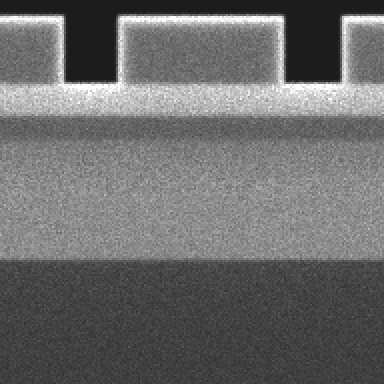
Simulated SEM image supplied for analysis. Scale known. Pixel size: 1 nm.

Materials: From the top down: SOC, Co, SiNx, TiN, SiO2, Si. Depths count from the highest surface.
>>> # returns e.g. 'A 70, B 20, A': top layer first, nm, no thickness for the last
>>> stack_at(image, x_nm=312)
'empty 68, Co 32, SiNx 24, TiN 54, SiO2 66, Si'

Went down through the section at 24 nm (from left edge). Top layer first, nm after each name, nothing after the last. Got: SOC 68, Co 32, SiNx 24, TiN 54, SiO2 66, Si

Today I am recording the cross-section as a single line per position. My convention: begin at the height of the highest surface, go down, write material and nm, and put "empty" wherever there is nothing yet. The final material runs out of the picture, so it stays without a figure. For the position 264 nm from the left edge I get SOC 68, Co 32, SiNx 24, TiN 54, SiO2 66, Si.